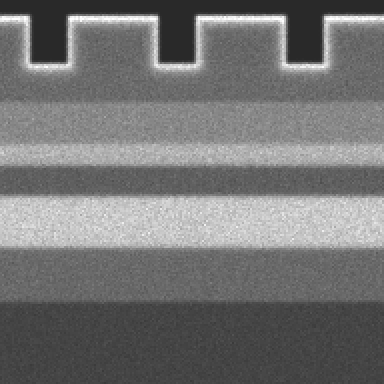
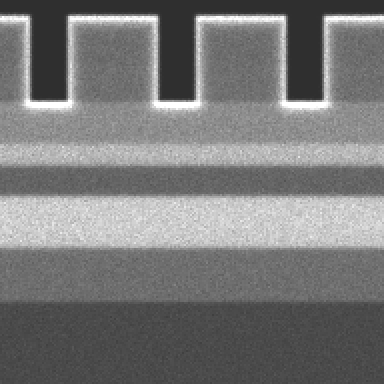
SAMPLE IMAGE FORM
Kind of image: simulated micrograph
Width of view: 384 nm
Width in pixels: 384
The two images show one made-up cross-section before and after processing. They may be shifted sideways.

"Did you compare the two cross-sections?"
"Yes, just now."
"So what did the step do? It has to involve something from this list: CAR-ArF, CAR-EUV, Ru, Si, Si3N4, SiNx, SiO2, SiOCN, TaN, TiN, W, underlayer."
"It removed underlayer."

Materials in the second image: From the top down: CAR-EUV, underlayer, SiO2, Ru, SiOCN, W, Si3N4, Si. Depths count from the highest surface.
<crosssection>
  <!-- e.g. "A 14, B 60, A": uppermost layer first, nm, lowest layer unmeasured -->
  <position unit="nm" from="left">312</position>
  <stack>empty 86, SiO2 42, Ru 22, SiOCN 30, W 52, Si3N4 54, Si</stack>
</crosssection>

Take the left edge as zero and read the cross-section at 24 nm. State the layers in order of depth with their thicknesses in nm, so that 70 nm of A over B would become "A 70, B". CAR-EUV 48, underlayer 38, SiO2 42, Ru 22, SiOCN 30, W 52, Si3N4 54, Si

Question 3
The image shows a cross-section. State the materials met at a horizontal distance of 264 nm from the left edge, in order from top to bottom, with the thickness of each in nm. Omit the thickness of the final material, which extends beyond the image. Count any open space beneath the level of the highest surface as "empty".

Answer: CAR-EUV 48, underlayer 38, SiO2 42, Ru 22, SiOCN 30, W 52, Si3N4 54, Si